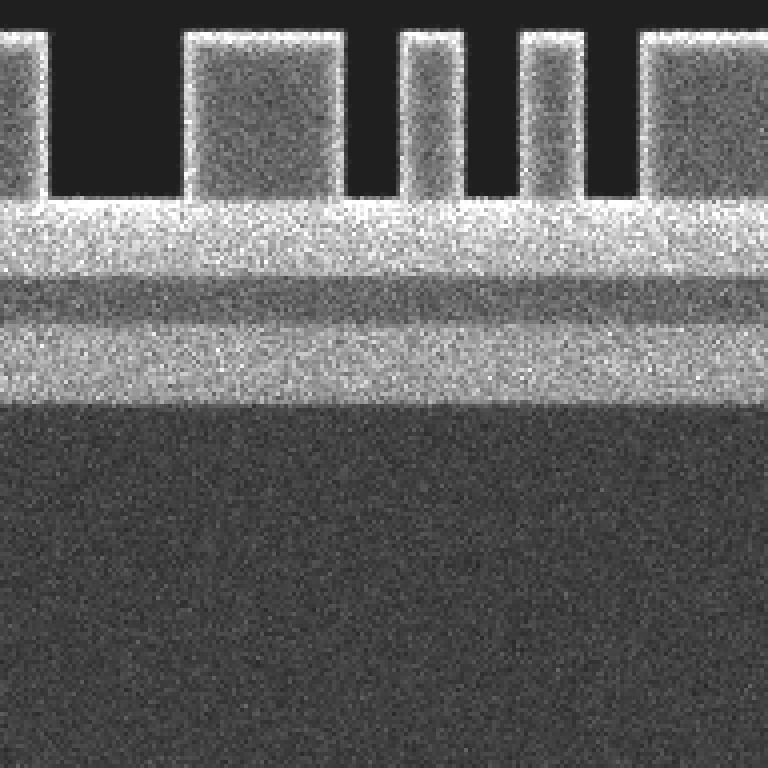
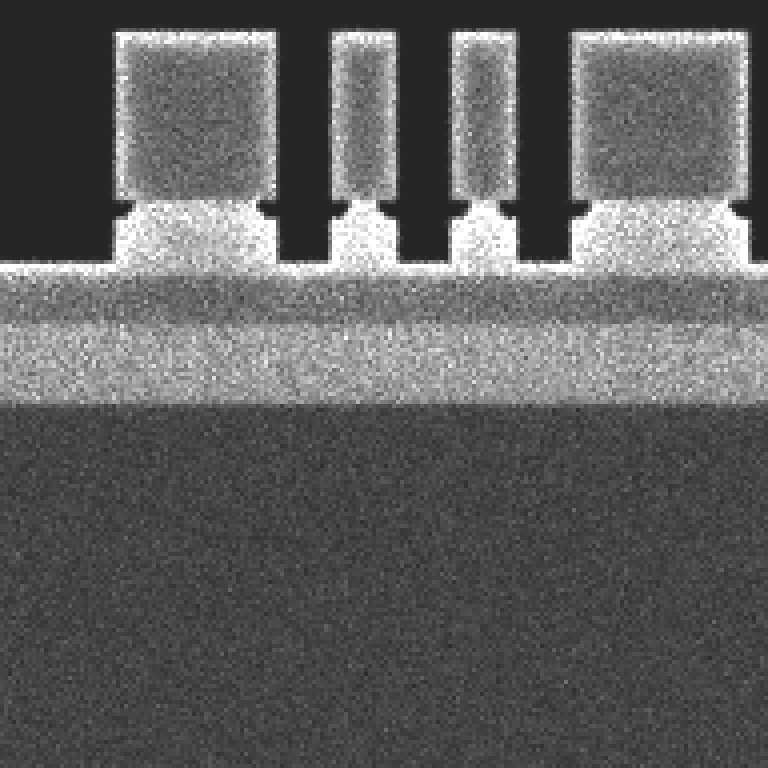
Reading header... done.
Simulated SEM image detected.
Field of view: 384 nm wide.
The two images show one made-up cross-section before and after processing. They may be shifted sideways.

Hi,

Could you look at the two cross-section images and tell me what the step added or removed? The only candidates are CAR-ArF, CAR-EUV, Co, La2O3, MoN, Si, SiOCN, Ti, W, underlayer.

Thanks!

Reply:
removed W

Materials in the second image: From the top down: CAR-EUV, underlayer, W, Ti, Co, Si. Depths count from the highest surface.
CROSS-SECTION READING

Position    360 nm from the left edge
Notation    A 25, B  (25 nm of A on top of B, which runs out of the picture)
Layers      CAR-EUV 50, underlayer 34, W 38, Ti 24, Co 40, Si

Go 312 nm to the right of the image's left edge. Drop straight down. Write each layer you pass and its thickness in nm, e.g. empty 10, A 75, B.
CAR-EUV 50, underlayer 34, W 38, Ti 24, Co 40, Si